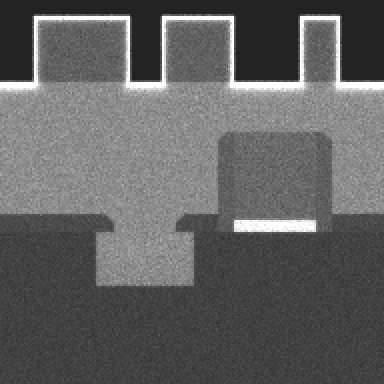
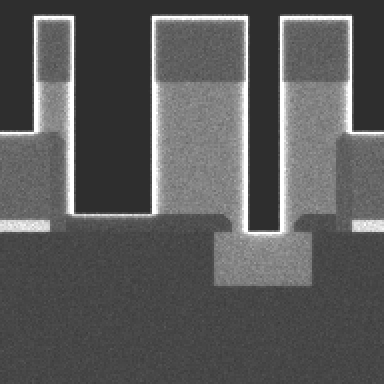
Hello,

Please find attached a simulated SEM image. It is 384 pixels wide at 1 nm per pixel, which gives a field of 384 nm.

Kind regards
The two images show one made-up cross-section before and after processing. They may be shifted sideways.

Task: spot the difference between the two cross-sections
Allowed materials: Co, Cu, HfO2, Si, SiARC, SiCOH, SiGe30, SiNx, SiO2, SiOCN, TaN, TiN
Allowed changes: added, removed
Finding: removed SiO2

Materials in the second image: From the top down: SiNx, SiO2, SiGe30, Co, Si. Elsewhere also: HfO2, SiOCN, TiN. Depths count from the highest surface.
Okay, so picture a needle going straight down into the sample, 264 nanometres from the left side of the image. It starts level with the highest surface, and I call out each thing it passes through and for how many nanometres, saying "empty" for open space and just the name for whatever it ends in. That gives empty 216, Co 54, Si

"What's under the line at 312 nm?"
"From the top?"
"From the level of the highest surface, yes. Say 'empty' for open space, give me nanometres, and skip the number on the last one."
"SiNx 66, SiO2 132, SiGe30 18, Si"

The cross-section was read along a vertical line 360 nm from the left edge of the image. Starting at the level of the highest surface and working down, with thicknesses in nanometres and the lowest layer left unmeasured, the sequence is empty 116, TiN 88, HfO2 12, Si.